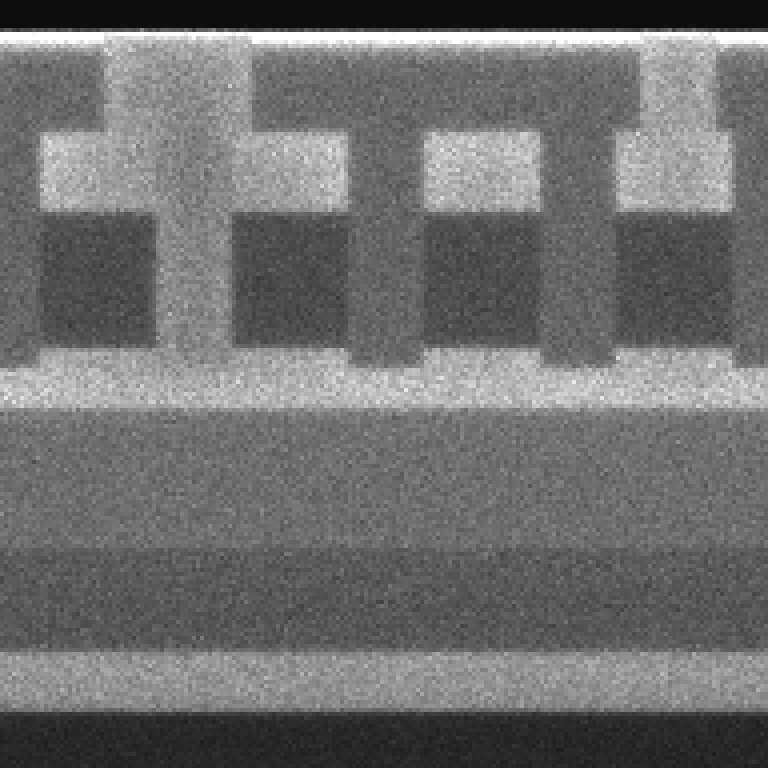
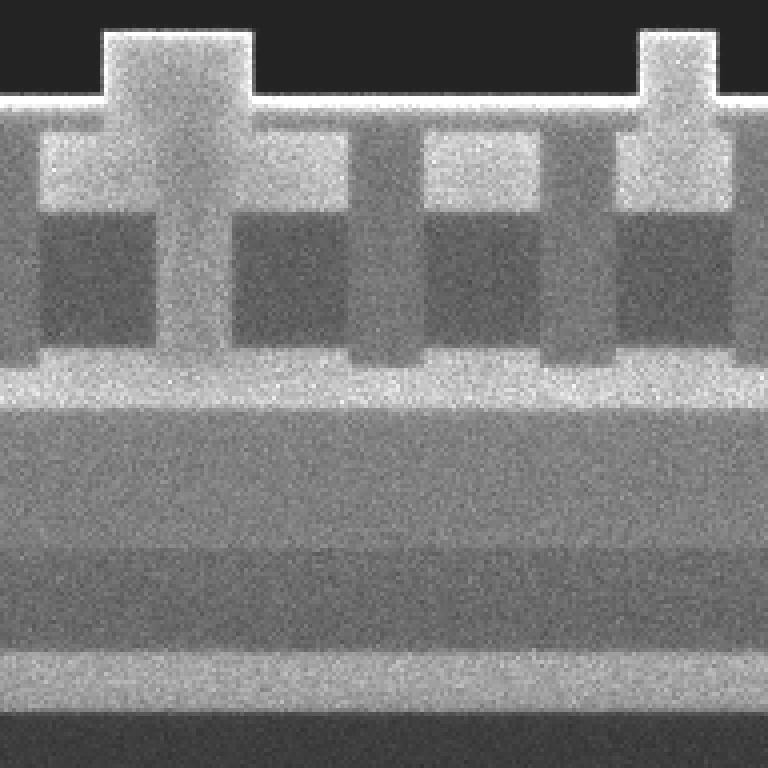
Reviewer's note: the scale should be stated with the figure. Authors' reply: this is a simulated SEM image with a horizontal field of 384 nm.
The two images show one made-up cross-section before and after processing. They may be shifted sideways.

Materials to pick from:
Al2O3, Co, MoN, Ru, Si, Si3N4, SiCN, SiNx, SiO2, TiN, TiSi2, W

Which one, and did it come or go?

SiO2 - removed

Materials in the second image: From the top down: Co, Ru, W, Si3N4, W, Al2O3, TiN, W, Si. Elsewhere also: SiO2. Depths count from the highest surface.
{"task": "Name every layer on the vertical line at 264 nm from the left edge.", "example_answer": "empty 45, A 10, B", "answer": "empty 32, SiO2 18, W 40, Si3N4 68, W 30, Al2O3 70, TiN 52, W 30, Si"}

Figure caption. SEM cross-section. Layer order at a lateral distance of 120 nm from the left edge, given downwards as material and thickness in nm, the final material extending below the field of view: Ru 50, W 40, Si3N4 68, W 30, Al2O3 70, TiN 52, W 30, Si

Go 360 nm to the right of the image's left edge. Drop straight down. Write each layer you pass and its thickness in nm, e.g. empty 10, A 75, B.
empty 32, SiO2 18, W 40, Si3N4 68, W 30, Al2O3 70, TiN 52, W 30, Si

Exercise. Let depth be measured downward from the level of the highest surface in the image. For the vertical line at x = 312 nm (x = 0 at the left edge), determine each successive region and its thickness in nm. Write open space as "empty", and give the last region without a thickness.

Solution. empty 32, SiO2 18, W 40, Si3N4 68, W 30, Al2O3 70, TiN 52, W 30, Si